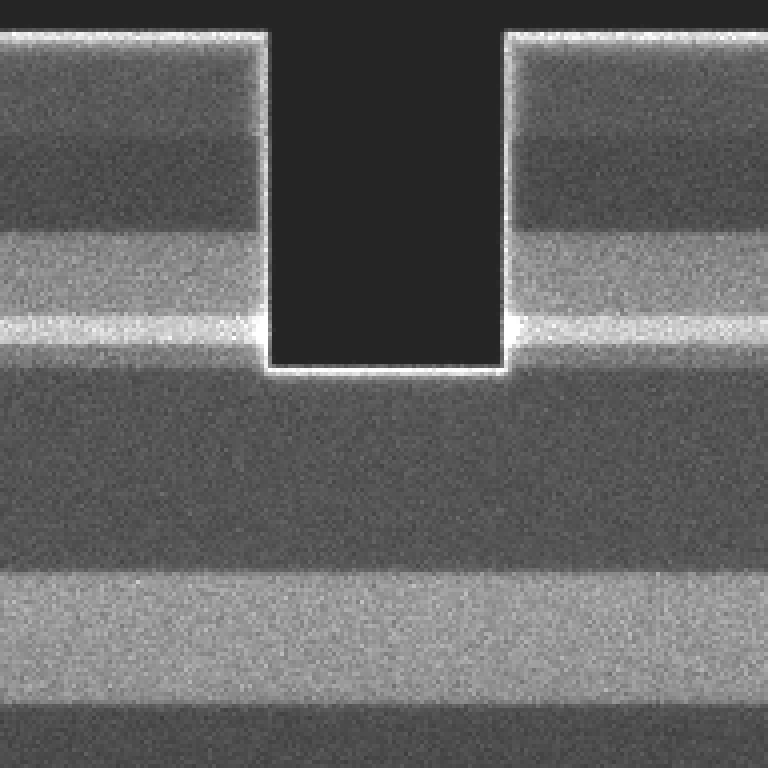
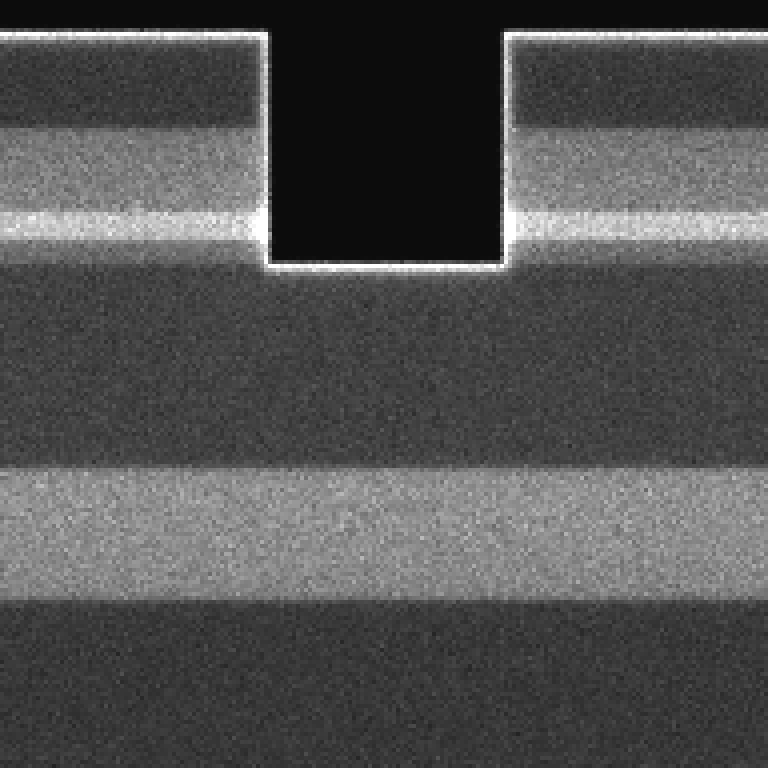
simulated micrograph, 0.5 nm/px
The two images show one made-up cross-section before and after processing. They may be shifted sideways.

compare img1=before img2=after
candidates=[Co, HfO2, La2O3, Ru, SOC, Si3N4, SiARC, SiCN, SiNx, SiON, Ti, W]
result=removed:SOC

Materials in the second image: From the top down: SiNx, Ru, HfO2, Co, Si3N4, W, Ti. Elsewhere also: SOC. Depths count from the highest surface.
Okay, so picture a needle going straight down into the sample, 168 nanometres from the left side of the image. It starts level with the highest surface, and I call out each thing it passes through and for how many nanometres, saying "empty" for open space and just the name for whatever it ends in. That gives empty 116, Si3N4 102, W 66, Ti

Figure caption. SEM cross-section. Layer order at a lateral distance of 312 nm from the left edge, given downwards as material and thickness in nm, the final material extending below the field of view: SiNx 48, Ru 42, HfO2 14, Co 12, Si3N4 102, W 66, Ti